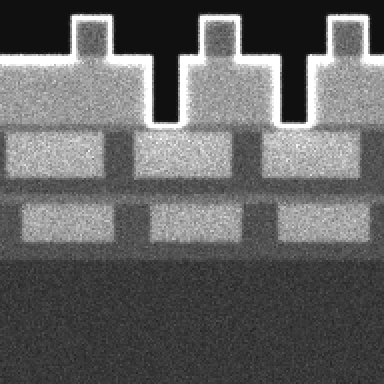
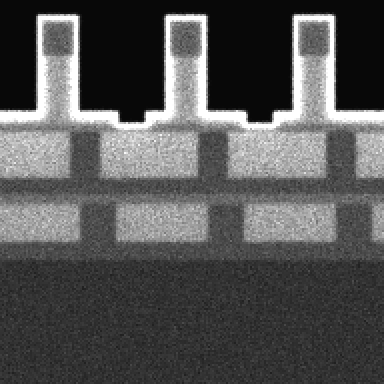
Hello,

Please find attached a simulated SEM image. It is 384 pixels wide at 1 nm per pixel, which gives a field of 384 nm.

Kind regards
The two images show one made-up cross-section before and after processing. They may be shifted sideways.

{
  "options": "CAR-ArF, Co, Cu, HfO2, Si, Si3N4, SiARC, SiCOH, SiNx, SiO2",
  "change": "removed",
  "material": "SiO2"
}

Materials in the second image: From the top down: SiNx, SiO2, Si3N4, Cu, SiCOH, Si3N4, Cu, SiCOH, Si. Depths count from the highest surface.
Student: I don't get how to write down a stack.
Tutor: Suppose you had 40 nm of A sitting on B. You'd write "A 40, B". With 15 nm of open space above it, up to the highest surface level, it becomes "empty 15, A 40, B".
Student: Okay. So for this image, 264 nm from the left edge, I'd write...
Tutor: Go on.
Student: empty 108, Si3N4 8, Cu 46, SiCOH 16, Si3N4 10, Cu 38, SiCOH 18, Si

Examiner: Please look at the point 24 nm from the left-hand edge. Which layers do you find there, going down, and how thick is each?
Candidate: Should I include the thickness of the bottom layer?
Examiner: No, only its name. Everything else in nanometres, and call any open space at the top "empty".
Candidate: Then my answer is empty 96, SiO2 12, Si3N4 8, Cu 46, SiCOH 16, Si3N4 10, Cu 38, SiCOH 18, Si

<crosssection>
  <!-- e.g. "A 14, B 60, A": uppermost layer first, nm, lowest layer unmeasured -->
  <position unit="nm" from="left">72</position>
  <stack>SiNx 40, SiO2 68, Si3N4 8, SiCOH 62, Si3N4 10, Cu 38, SiCOH 18, Si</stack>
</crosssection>